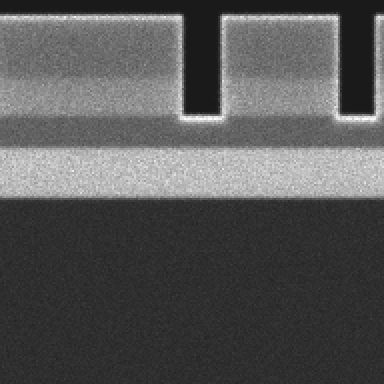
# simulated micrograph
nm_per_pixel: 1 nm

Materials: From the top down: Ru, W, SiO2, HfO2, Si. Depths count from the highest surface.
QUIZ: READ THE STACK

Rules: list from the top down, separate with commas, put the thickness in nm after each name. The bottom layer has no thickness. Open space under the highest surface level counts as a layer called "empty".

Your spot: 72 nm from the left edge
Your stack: Ru 62, W 38, SiO2 32, HfO2 50, Si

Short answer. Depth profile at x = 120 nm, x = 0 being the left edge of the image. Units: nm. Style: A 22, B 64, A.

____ Ru 62, W 38, SiO2 32, HfO2 50, Si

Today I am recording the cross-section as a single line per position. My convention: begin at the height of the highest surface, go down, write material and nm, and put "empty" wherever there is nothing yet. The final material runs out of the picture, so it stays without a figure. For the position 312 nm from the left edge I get Ru 62, W 38, SiO2 32, HfO2 50, Si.